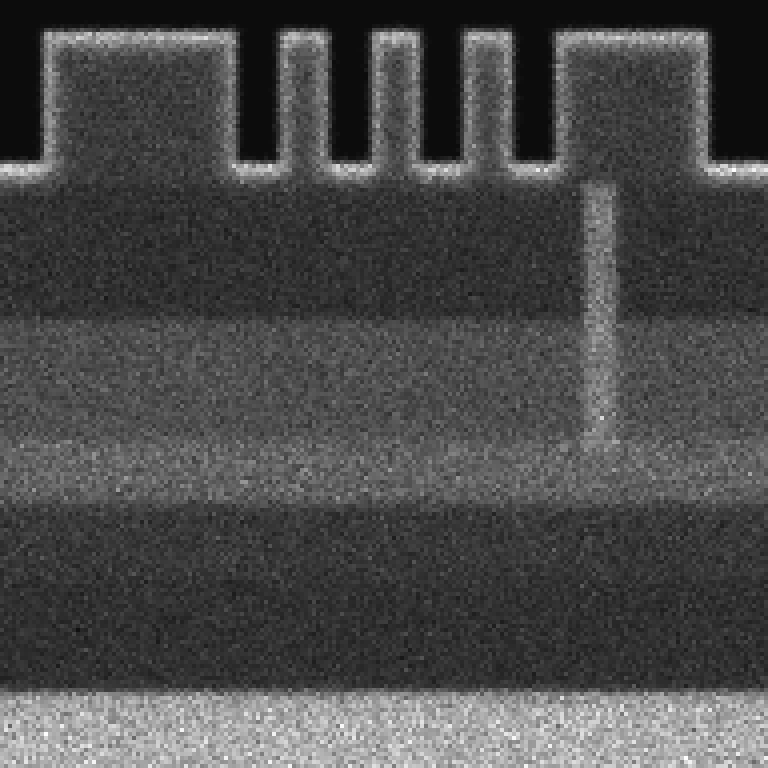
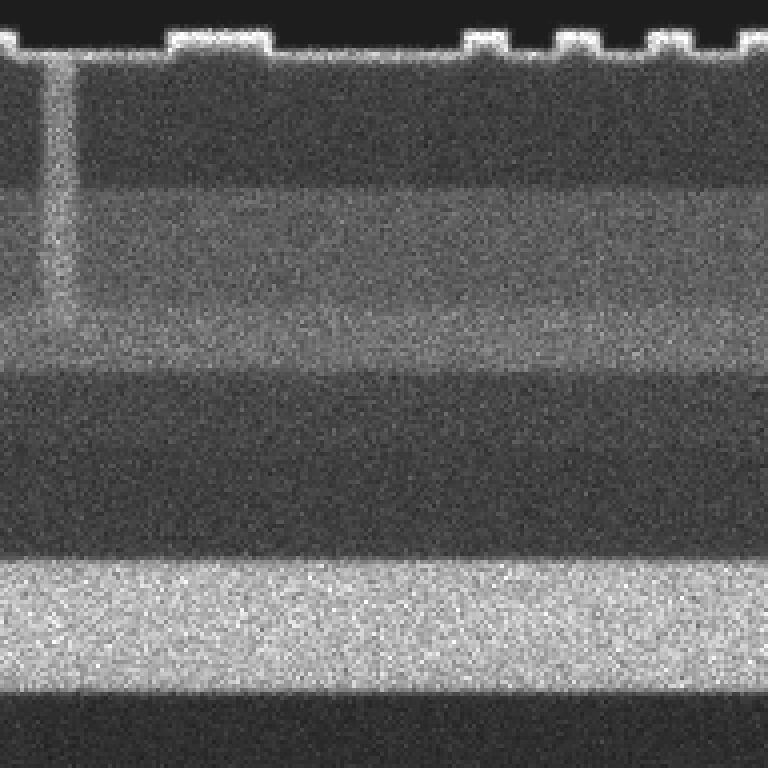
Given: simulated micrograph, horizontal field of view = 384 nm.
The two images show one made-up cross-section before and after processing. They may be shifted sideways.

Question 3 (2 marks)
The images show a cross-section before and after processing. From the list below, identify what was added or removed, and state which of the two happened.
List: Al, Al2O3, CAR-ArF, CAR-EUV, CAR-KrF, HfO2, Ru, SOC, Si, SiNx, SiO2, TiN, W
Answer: SOC was removed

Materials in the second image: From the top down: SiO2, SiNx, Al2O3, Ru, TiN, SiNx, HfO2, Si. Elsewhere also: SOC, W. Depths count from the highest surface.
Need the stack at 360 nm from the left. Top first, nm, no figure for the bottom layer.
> empty 10, SiNx 68, Al2O3 60, Ru 32, TiN 38, SiNx 56, HfO2 66, Si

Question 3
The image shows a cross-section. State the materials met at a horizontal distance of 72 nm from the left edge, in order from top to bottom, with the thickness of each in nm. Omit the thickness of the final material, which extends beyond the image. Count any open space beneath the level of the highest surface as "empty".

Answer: empty 10, SiNx 68, Al2O3 60, Ru 32, TiN 38, SiNx 56, HfO2 66, Si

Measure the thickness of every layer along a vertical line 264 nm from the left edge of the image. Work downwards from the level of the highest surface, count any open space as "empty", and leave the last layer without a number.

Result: empty 10, SiNx 68, Al2O3 60, Ru 32, TiN 38, SiNx 56, HfO2 66, Si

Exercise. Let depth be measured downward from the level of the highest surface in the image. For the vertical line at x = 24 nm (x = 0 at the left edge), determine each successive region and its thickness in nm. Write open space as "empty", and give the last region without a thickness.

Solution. empty 10, W 136, Ru 24, TiN 38, SiNx 56, HfO2 66, Si